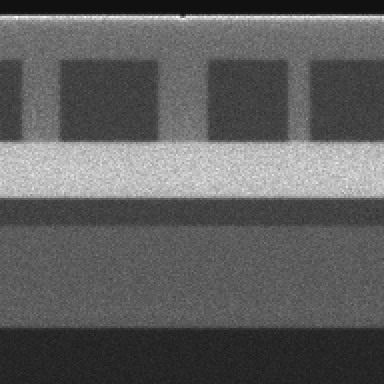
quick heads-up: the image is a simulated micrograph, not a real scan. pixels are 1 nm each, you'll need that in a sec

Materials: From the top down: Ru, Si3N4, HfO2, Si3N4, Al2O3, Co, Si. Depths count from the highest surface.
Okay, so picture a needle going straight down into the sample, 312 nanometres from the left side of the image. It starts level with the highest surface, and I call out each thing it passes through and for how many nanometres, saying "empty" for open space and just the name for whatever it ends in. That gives Ru 44, Si3N4 82, HfO2 56, Si3N4 28, Al2O3 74, Co 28, Si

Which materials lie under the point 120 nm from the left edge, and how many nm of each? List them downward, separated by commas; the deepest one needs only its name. Ru 44, Si3N4 82, HfO2 56, Si3N4 28, Al2O3 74, Co 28, Si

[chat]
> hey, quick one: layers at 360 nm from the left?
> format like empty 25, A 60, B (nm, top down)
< Ru 44, Si3N4 82, HfO2 56, Si3N4 28, Al2O3 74, Co 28, Si